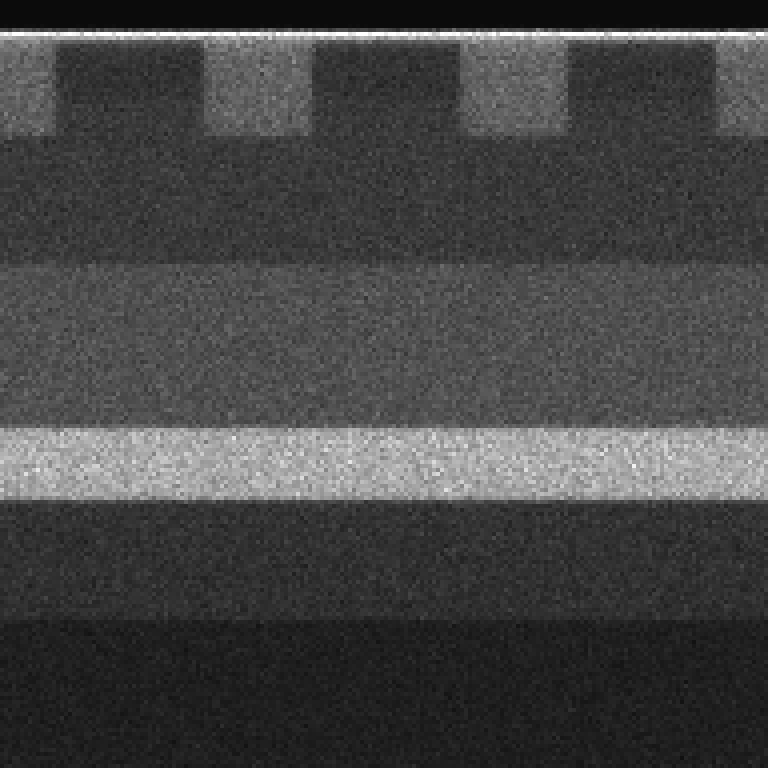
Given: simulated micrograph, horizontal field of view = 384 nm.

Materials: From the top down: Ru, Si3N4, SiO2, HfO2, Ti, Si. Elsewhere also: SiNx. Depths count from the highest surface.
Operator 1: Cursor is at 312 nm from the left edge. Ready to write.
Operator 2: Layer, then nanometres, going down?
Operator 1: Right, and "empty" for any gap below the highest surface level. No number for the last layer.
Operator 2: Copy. SiNx 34, Si3N4 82, SiO2 82, HfO2 36, Ti 60, Si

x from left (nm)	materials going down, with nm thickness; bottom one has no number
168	SiNx 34, Si3N4 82, SiO2 82, HfO2 36, Ti 60, Si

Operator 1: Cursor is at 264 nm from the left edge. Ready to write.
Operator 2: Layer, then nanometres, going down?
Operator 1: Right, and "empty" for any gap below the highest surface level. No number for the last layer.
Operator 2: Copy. Ru 52, Si3N4 64, SiO2 82, HfO2 36, Ti 60, Si